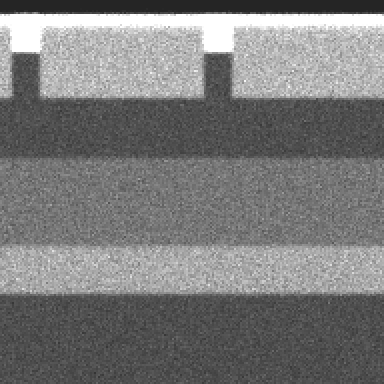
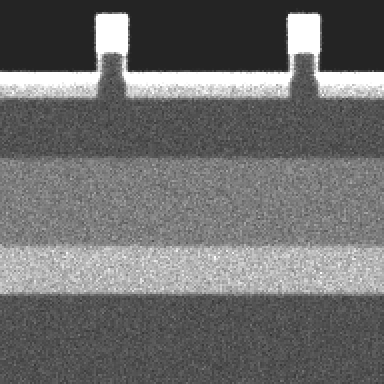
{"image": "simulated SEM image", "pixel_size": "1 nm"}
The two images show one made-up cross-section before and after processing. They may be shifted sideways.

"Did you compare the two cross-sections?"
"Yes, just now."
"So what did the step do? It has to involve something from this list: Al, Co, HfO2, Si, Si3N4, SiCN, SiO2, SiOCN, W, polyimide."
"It removed SiO2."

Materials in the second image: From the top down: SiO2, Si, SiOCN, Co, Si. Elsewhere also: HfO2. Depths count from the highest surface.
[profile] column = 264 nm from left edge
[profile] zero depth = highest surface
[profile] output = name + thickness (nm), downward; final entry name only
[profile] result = empty 58, SiO2 24, Si 60, SiOCN 88, Co 48, Si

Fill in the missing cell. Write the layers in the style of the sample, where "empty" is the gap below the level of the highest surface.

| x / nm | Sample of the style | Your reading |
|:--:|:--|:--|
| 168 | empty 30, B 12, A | empty 58, SiO2 24, Si 60, SiOCN 88, Co 48, Si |